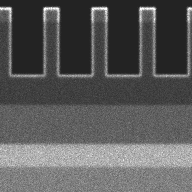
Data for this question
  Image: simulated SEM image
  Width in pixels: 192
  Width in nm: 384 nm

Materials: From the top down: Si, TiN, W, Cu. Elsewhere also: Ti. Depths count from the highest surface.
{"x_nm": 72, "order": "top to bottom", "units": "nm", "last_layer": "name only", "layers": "empty 134, Si 60, TiN 78, W 46, Cu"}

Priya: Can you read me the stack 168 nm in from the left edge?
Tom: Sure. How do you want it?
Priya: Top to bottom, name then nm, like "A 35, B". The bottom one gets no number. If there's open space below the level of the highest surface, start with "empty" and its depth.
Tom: empty 134, Si 60, TiN 78, W 46, Cu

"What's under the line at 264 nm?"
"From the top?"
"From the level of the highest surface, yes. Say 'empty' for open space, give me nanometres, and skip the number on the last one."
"empty 134, Si 60, TiN 78, W 46, Cu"